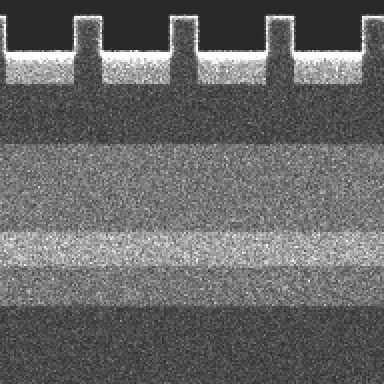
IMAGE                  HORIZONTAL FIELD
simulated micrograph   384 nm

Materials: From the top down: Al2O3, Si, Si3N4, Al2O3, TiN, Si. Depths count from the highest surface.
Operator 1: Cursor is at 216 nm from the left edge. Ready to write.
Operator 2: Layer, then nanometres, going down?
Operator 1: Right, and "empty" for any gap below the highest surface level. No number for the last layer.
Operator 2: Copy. empty 36, Al2O3 32, Si 60, Si3N4 88, Al2O3 34, TiN 40, Si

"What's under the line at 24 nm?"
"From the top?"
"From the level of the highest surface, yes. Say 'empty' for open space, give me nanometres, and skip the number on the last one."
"empty 36, Al2O3 32, Si 60, Si3N4 88, Al2O3 34, TiN 40, Si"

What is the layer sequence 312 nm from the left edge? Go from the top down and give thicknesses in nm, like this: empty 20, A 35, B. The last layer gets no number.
empty 36, Al2O3 32, Si 60, Si3N4 88, Al2O3 34, TiN 40, Si